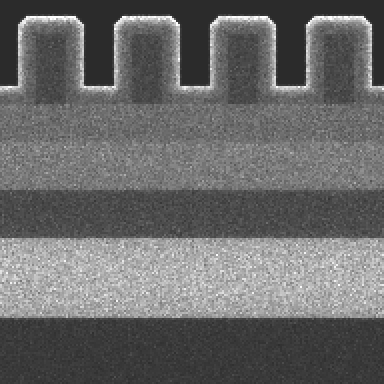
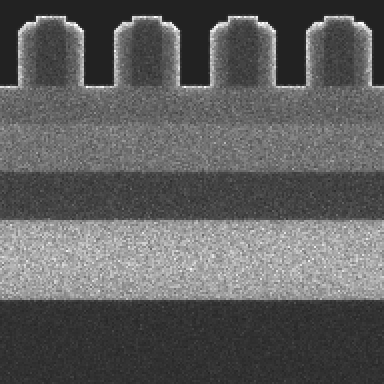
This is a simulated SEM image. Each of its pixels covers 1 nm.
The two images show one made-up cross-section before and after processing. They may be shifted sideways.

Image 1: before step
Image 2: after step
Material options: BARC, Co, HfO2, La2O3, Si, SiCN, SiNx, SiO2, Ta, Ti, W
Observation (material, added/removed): SiO2, removed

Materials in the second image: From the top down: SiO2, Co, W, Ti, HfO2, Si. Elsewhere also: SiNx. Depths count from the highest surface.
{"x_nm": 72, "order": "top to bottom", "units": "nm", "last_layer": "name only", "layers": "empty 6, SiO2 64, Co 38, W 48, Ti 48, HfO2 80, Si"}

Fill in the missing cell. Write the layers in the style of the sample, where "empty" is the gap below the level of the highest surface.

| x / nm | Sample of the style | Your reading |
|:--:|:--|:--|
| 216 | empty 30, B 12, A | empty 8, SiO2 62, Co 38, W 48, Ti 48, HfO2 80, Si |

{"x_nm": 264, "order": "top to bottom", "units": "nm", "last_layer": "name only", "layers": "empty 6, SiO2 64, Co 38, W 48, Ti 48, HfO2 80, Si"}